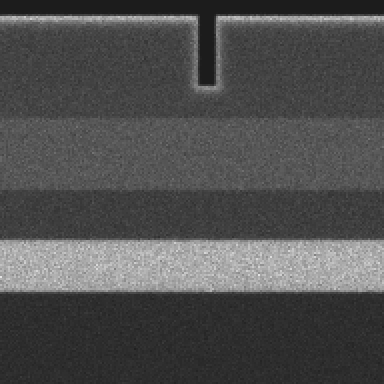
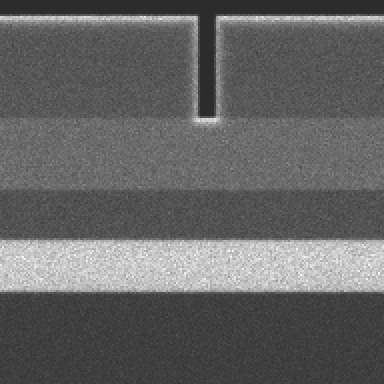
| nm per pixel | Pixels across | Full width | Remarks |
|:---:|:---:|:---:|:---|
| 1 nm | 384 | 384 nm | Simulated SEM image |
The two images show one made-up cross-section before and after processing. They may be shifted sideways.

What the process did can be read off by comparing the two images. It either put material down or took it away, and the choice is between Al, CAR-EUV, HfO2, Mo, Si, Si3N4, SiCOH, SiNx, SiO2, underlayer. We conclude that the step removed underlayer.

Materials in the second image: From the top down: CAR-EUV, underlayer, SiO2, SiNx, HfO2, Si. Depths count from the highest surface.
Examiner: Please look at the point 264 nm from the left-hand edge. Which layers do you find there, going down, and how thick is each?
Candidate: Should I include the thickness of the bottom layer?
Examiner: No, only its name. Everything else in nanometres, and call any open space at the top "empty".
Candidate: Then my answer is CAR-EUV 70, underlayer 32, SiO2 72, SiNx 50, HfO2 52, Si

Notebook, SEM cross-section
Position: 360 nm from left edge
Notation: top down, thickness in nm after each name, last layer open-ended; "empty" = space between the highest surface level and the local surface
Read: CAR-EUV 70, underlayer 32, SiO2 72, SiNx 50, HfO2 52, Si